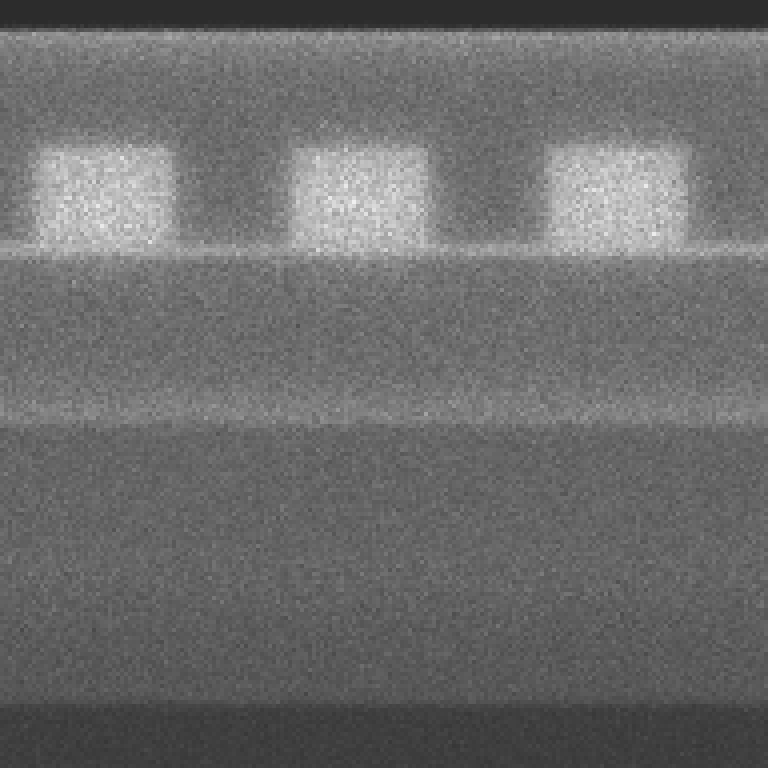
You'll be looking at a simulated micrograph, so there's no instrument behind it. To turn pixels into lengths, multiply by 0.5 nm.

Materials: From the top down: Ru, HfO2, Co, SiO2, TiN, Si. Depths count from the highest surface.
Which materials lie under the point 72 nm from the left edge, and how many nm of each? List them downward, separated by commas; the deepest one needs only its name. Ru 58, HfO2 54, Co 84, SiO2 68, TiN 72, Si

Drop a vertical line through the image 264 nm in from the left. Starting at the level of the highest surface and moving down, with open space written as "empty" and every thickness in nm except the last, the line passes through Ru 106, HfO2 6, Co 84, SiO2 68, TiN 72, Si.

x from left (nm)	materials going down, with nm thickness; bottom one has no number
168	Ru 58, HfO2 54, Co 84, SiO2 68, TiN 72, Si